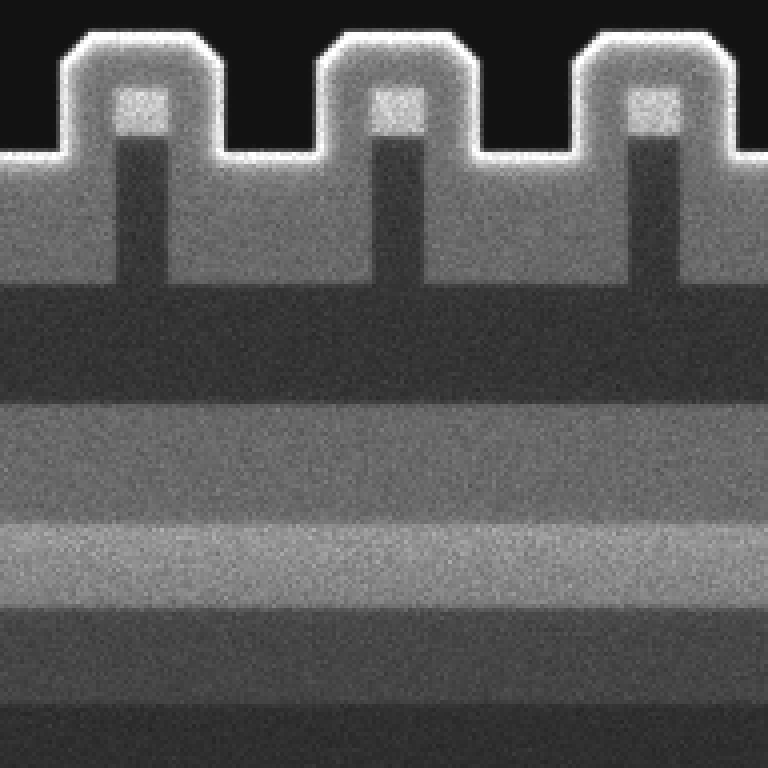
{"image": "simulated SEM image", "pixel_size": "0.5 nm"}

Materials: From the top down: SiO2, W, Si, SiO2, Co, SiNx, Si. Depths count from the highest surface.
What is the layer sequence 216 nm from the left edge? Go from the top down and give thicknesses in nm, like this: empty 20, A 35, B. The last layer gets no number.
SiO2 126, Si 60, SiO2 60, Co 42, SiNx 48, Si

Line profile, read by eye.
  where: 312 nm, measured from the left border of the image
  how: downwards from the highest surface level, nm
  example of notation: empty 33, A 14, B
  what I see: SiO2 126, Si 60, SiO2 60, Co 42, SiNx 48, Si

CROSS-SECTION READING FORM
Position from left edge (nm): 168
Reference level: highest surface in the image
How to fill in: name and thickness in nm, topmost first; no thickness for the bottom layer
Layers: empty 4, SiO2 122, Si 60, SiO2 60, Co 42, SiNx 48, Si